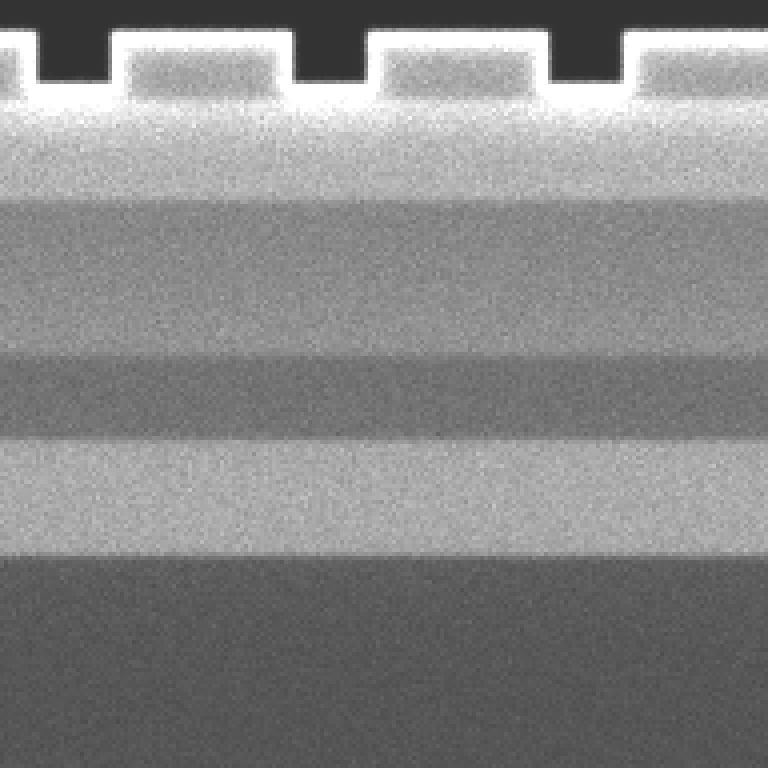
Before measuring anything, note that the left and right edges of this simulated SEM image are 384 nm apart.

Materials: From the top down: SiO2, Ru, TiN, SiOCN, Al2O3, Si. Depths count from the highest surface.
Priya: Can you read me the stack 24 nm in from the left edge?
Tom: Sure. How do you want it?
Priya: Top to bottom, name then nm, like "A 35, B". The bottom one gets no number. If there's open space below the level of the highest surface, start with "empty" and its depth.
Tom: empty 26, SiO2 8, Ru 50, TiN 78, SiOCN 42, Al2O3 58, Si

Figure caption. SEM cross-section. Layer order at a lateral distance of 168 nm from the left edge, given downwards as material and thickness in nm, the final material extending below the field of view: empty 26, SiO2 8, Ru 50, TiN 78, SiOCN 42, Al2O3 58, Si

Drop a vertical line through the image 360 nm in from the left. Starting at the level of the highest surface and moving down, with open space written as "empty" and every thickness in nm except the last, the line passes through SiO2 34, Ru 50, TiN 78, SiOCN 42, Al2O3 58, Si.